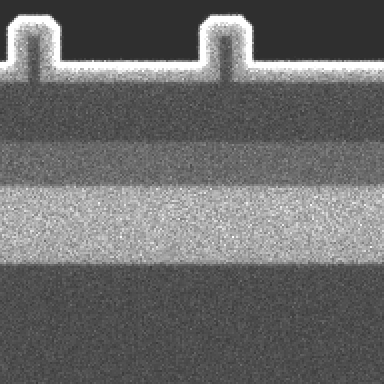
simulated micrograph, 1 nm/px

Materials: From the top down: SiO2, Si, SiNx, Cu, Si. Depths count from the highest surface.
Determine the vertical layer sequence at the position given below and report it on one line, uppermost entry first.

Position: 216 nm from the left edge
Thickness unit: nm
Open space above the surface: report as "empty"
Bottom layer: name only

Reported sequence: SiO2 66, Si 60, SiNx 44, Cu 78, Si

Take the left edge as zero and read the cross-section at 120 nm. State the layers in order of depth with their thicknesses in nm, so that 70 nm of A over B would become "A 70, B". empty 46, SiO2 20, Si 60, SiNx 44, Cu 78, Si